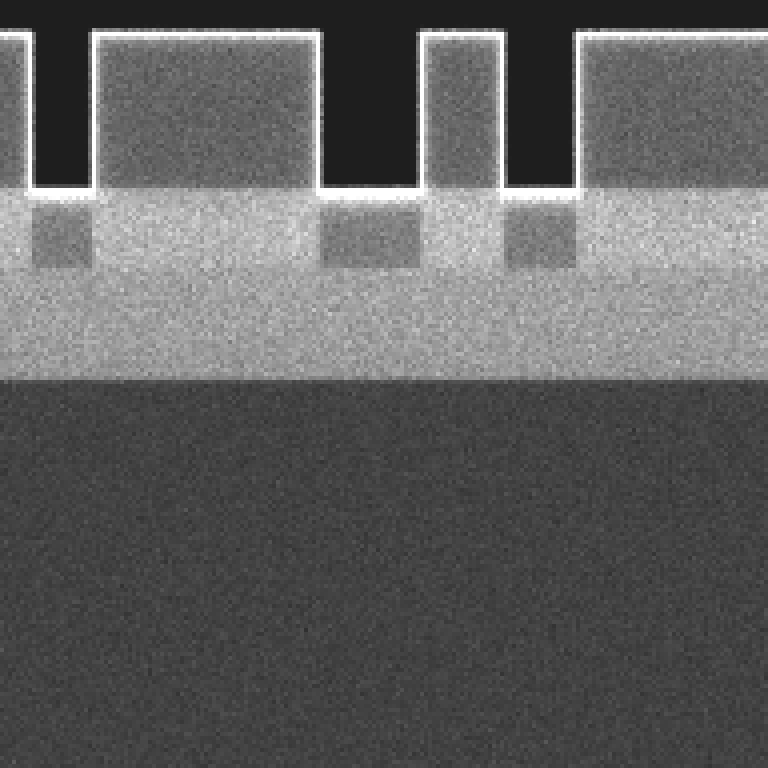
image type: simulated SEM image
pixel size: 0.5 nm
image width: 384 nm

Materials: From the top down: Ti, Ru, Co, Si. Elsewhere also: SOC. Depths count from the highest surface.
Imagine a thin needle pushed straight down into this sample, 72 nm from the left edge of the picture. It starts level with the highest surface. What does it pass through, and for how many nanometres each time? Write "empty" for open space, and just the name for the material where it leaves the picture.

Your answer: Ti 78, Ru 40, Co 56, Si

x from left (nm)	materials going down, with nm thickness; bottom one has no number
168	empty 78, SOC 40, Co 56, Si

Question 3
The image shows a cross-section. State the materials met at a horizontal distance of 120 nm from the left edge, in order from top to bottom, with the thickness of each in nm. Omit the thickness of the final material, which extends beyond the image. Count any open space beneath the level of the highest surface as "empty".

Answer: Ti 78, Ru 40, Co 56, Si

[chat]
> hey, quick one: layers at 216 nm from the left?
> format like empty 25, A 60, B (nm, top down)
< Ti 78, Ru 40, Co 56, Si